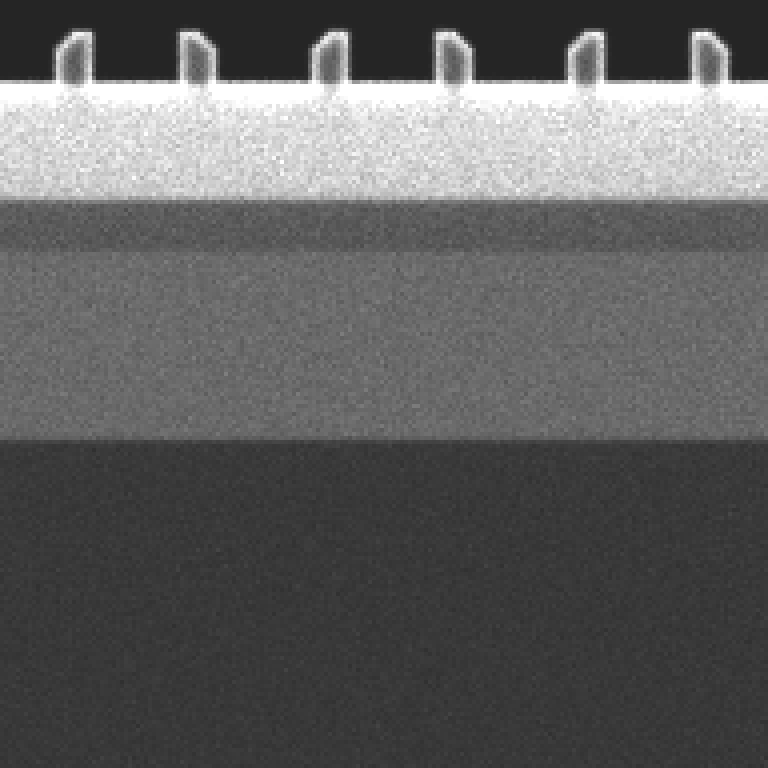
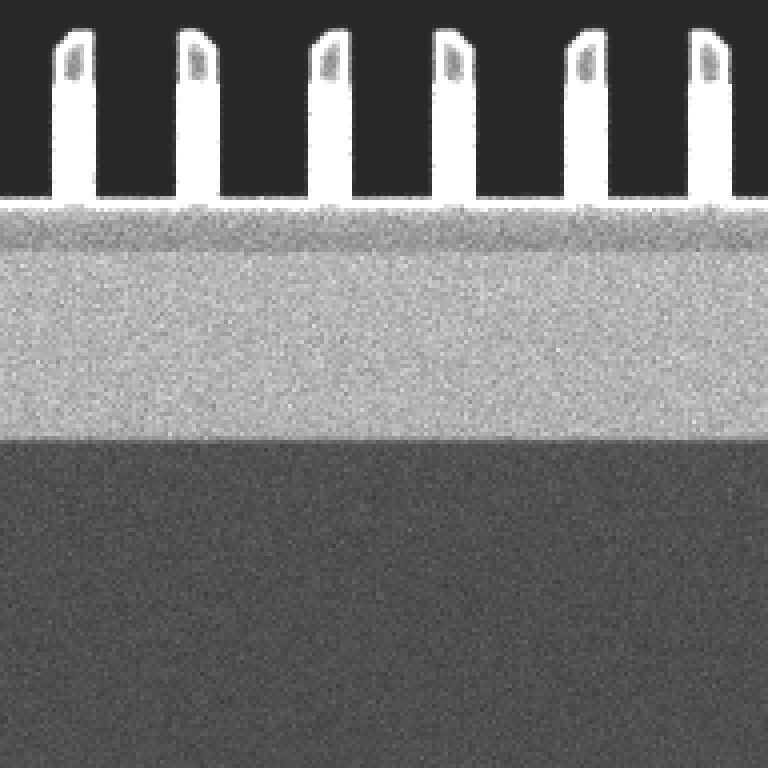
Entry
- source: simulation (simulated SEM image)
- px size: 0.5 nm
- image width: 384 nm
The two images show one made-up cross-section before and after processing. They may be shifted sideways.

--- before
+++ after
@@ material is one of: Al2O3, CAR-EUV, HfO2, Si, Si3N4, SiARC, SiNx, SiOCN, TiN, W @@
HfO2 removed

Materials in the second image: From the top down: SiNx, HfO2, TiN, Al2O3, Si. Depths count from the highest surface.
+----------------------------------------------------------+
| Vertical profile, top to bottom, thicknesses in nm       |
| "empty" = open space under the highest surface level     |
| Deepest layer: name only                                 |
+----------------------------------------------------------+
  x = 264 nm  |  empty 84, TiN 26, Al2O3 94, Si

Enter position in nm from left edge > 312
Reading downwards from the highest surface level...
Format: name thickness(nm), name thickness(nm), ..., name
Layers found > empty 84, TiN 26, Al2O3 94, Si